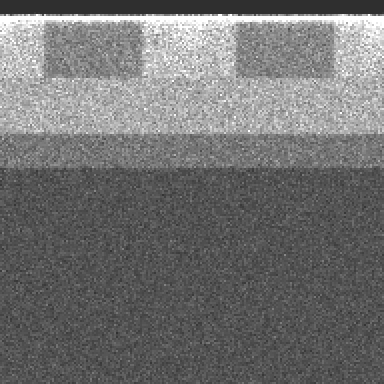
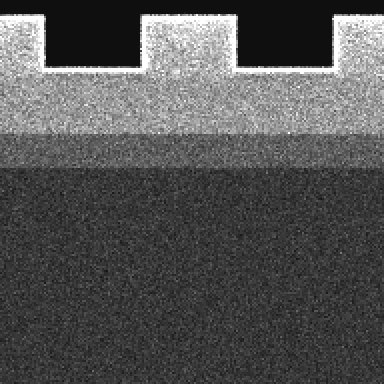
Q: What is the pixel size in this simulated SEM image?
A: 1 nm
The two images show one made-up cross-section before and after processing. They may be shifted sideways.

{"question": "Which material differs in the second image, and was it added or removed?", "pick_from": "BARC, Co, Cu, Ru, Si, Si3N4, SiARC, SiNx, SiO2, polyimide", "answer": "Si3N4, removed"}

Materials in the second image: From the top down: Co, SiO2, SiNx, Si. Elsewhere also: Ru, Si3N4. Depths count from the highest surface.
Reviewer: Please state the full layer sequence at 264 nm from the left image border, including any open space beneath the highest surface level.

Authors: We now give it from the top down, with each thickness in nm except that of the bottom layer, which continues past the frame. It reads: empty 52, Si3N4 10, SiO2 56, SiNx 34, Si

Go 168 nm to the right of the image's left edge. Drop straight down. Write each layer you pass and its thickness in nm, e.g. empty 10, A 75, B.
Co 62, SiO2 56, SiNx 34, Si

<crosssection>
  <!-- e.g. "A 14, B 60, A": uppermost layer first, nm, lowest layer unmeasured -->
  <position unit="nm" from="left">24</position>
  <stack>Co 62, SiO2 56, SiNx 34, Si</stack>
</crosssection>